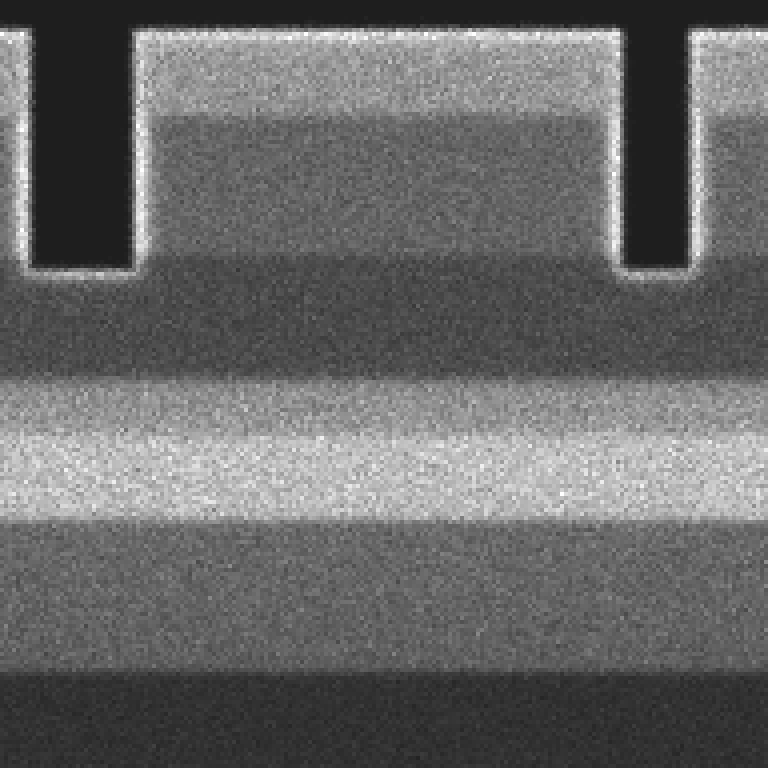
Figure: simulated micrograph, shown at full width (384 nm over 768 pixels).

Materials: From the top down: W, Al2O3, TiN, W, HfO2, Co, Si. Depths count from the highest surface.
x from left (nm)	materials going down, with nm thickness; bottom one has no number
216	W 42, Al2O3 70, TiN 62, W 28, HfO2 42, Co 76, Si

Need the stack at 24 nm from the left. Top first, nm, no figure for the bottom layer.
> empty 120, TiN 54, W 28, HfO2 42, Co 76, Si